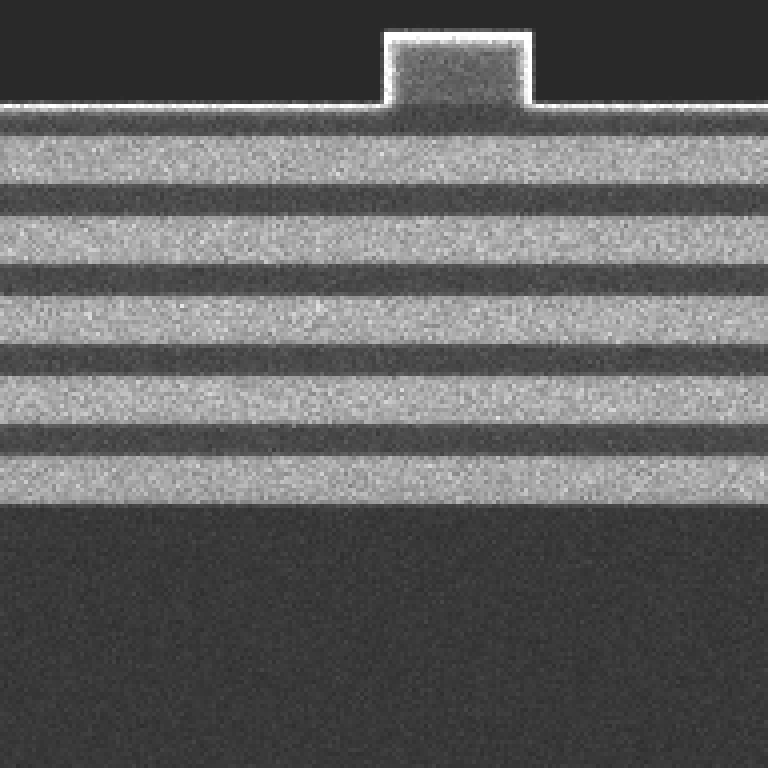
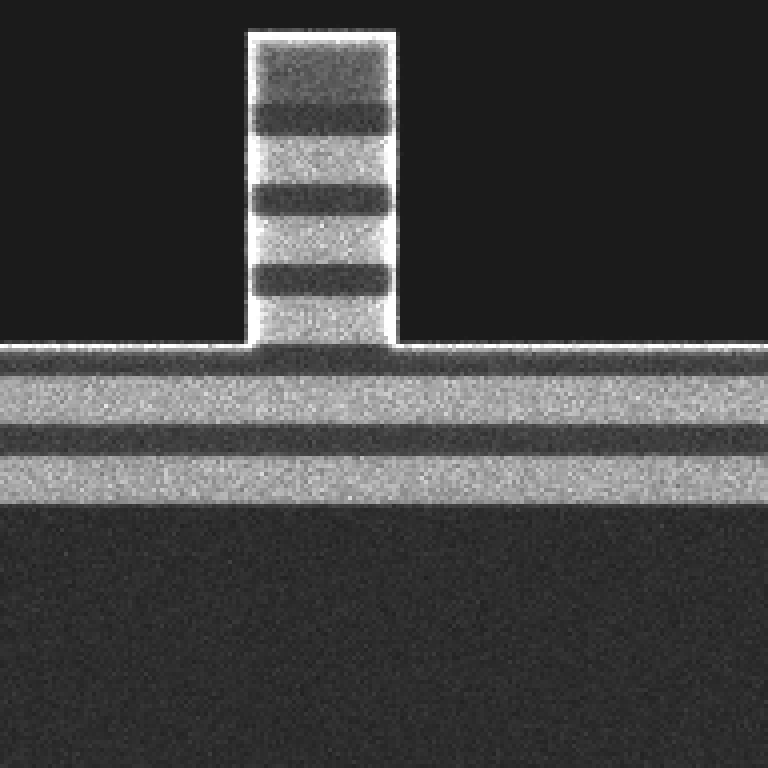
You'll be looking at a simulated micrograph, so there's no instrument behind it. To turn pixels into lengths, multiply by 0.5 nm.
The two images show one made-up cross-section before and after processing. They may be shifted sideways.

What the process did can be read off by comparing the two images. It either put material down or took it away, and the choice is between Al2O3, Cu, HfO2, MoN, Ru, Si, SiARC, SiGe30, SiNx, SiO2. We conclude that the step removed HfO2 and SiNx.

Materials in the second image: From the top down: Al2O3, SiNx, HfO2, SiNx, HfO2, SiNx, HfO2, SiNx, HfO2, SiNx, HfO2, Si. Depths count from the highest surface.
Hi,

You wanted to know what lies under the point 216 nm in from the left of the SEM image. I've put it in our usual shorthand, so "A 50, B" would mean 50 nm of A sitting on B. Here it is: empty 156, SiNx 16, HfO2 24, SiNx 16, HfO2 24, Si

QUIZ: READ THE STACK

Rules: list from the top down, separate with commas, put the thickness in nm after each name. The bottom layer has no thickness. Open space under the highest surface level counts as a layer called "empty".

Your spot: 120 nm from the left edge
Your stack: empty 156, SiNx 16, HfO2 24, SiNx 16, HfO2 24, Si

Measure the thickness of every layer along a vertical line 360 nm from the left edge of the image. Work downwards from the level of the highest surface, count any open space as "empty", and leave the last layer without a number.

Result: empty 156, SiNx 16, HfO2 24, SiNx 16, HfO2 24, Si